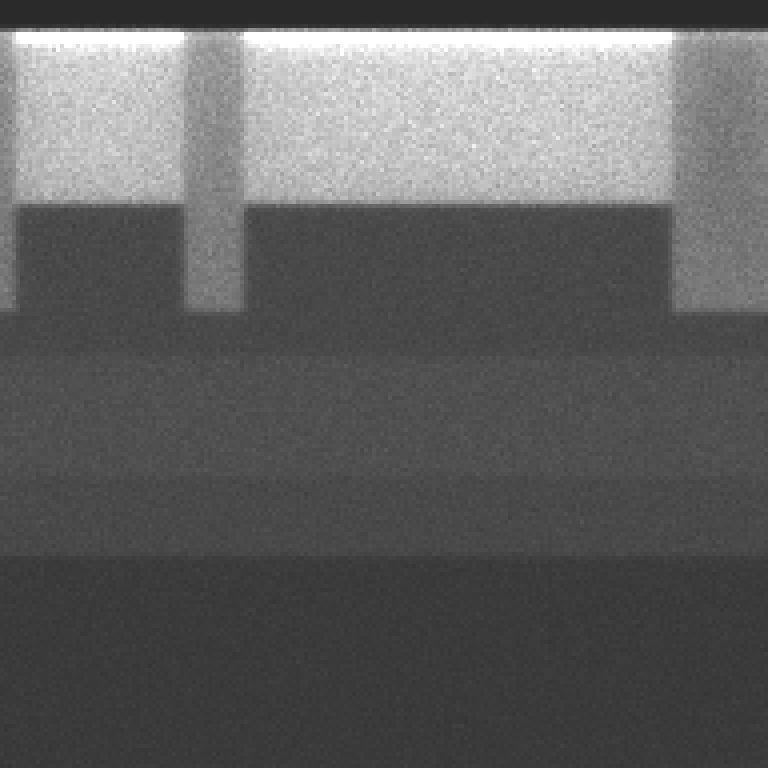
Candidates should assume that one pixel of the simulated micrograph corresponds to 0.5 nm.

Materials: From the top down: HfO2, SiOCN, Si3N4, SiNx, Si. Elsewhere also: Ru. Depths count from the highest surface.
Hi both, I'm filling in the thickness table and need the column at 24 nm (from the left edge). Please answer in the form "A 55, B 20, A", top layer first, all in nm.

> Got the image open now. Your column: HfO2 86, SiOCN 76, Si3N4 60, SiNx 40, Si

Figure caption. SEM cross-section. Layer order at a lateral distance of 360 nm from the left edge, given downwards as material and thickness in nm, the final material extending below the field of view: Ru 140, SiOCN 22, Si3N4 60, SiNx 40, Si